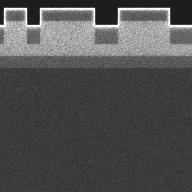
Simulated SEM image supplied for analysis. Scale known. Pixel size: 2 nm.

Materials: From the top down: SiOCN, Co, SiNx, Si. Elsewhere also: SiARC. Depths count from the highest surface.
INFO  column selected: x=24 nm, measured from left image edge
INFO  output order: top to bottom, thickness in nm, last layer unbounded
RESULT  SiOCN 26, Co 70, SiNx 24, Si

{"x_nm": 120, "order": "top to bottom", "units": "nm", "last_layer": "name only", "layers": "SiOCN 26, Co 70, SiNx 24, Si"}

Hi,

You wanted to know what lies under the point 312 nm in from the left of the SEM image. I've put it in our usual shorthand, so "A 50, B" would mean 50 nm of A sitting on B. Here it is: SiOCN 26, Co 70, SiNx 24, Si